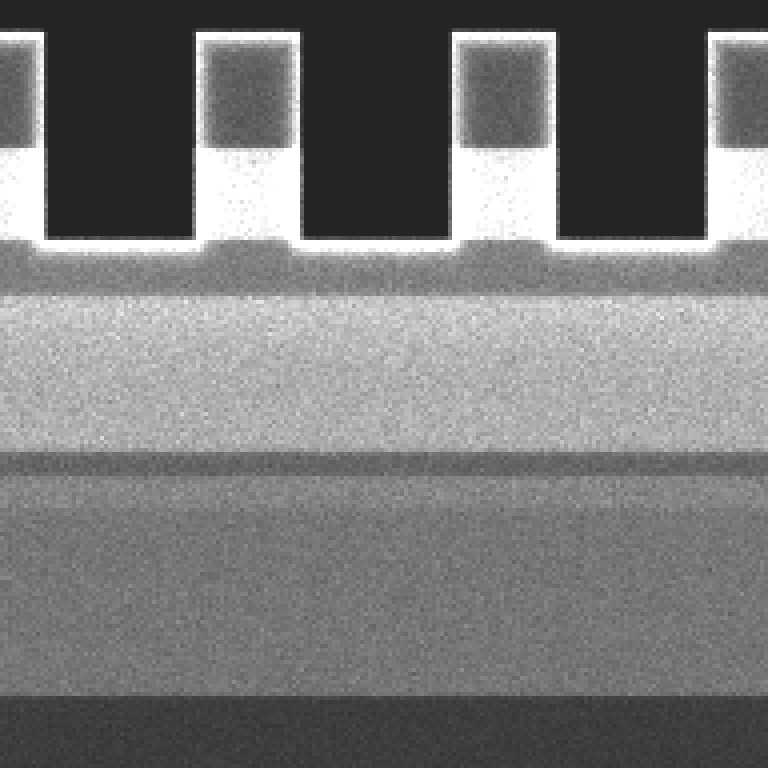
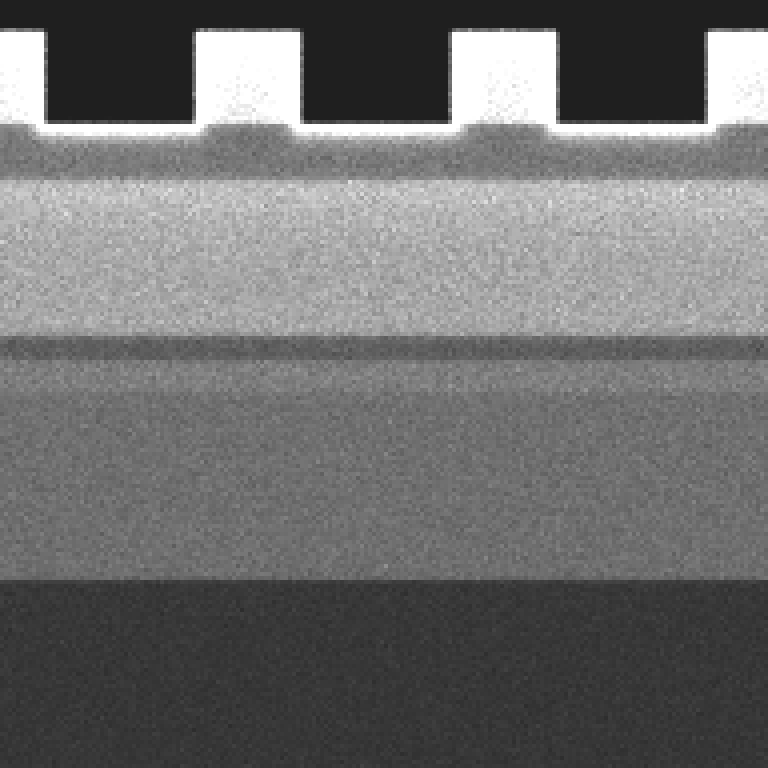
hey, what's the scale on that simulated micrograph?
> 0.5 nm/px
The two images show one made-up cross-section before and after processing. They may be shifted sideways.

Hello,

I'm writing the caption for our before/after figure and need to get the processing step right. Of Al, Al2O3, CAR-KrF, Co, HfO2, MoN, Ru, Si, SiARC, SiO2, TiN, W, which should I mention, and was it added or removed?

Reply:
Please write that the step removed SiARC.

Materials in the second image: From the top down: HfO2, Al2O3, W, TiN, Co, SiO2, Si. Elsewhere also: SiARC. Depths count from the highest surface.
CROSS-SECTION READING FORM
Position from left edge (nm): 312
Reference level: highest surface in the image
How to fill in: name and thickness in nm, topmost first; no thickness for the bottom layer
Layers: empty 46, Al2O3 28, W 78, TiN 12, Co 16, SiO2 94, Si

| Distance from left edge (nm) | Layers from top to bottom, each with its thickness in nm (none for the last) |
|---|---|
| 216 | empty 46, Al2O3 28, W 78, TiN 12, Co 16, SiO2 94, Si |